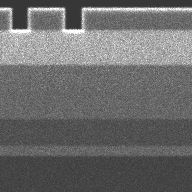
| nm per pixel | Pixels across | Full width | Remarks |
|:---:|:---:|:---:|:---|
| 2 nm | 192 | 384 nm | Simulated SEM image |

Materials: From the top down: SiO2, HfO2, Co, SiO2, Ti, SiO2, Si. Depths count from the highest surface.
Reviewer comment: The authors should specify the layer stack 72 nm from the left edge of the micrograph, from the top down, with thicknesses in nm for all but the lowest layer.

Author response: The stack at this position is SiO2 44, HfO2 70, Co 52, SiO2 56, Ti 54, SiO2 20, Si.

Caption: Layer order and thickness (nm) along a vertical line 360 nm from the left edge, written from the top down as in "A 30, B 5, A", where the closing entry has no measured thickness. SiO2 44, HfO2 70, Co 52, SiO2 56, Ti 54, SiO2 20, Si